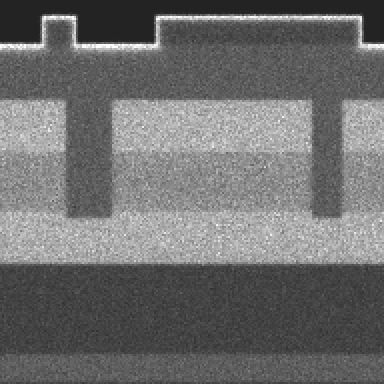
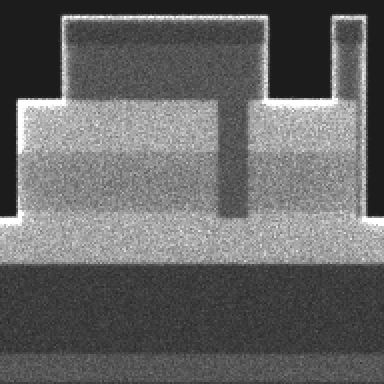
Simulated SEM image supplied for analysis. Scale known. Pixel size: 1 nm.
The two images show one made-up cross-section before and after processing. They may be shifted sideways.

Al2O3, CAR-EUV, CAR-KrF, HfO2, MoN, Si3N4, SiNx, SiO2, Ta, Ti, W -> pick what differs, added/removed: SiO2 removed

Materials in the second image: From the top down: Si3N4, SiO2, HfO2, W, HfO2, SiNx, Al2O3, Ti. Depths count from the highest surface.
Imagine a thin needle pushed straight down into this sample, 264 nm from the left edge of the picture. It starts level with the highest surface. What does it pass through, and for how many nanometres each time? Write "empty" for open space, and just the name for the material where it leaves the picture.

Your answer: Si3N4 28, SiO2 56, HfO2 52, W 60, HfO2 52, SiNx 90, Al2O3 28, Ti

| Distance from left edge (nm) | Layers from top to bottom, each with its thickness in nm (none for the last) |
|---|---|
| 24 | empty 84, HfO2 52, W 60, HfO2 52, SiNx 90, Al2O3 28, Ti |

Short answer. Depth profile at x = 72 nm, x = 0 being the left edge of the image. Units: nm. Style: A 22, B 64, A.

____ Si3N4 28, SiO2 56, HfO2 52, W 60, HfO2 52, SiNx 90, Al2O3 28, Ti